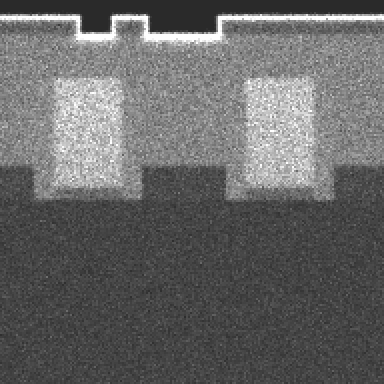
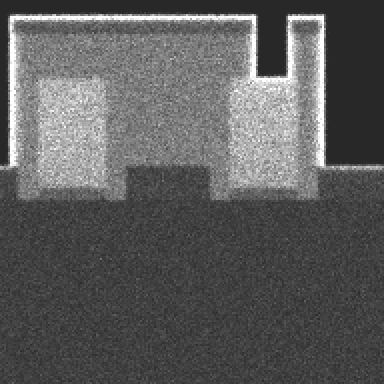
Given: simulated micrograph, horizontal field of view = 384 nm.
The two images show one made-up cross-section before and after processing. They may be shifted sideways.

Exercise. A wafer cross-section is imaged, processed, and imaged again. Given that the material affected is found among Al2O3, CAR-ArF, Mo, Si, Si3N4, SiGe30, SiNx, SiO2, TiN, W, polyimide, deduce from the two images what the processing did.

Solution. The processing removed SiO2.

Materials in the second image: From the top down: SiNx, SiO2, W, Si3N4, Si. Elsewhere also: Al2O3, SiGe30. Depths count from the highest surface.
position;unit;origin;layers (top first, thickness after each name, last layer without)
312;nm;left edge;SiNx 18, SiO2 50, Al2O3 116, Si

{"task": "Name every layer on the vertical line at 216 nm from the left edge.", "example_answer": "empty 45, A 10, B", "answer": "SiNx 18, SiO2 48, Al2O3 118, Si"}